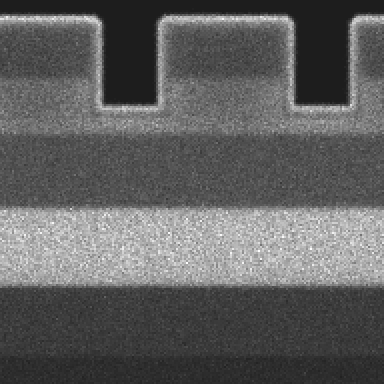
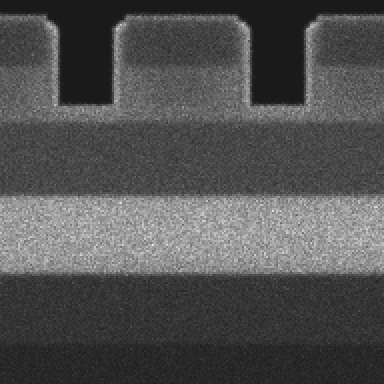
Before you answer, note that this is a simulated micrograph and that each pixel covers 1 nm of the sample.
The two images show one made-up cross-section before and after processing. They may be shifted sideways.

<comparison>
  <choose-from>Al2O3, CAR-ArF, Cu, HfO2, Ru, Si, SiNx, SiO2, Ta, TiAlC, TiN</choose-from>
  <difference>Al2O3 removed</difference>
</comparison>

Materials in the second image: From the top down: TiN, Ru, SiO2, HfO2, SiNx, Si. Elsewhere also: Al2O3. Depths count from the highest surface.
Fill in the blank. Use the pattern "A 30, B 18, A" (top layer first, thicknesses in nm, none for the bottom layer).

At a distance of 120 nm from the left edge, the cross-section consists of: empty 6, Al2O3 84, Ru 16, SiO2 74, HfO2 78, SiNx 70, Si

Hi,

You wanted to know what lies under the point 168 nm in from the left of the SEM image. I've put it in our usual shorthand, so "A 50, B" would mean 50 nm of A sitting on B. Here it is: TiN 50, Ru 56, SiO2 74, HfO2 78, SiNx 70, Si